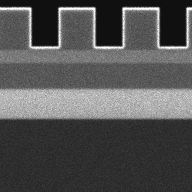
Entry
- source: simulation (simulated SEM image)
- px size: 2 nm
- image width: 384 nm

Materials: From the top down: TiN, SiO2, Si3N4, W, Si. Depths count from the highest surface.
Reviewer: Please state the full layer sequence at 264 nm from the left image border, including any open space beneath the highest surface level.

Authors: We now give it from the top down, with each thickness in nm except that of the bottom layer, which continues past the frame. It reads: TiN 84, SiO2 26, Si3N4 52, W 60, Si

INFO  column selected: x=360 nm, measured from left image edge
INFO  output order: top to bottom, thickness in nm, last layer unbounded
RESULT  empty 78, TiN 6, SiO2 26, Si3N4 52, W 60, Si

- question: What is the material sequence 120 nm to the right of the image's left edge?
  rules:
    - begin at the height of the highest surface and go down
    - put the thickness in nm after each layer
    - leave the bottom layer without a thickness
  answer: TiN 84, SiO2 26, Si3N4 52, W 60, Si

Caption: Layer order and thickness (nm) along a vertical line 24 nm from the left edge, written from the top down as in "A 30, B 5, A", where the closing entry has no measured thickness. TiN 84, SiO2 26, Si3N4 52, W 60, Si